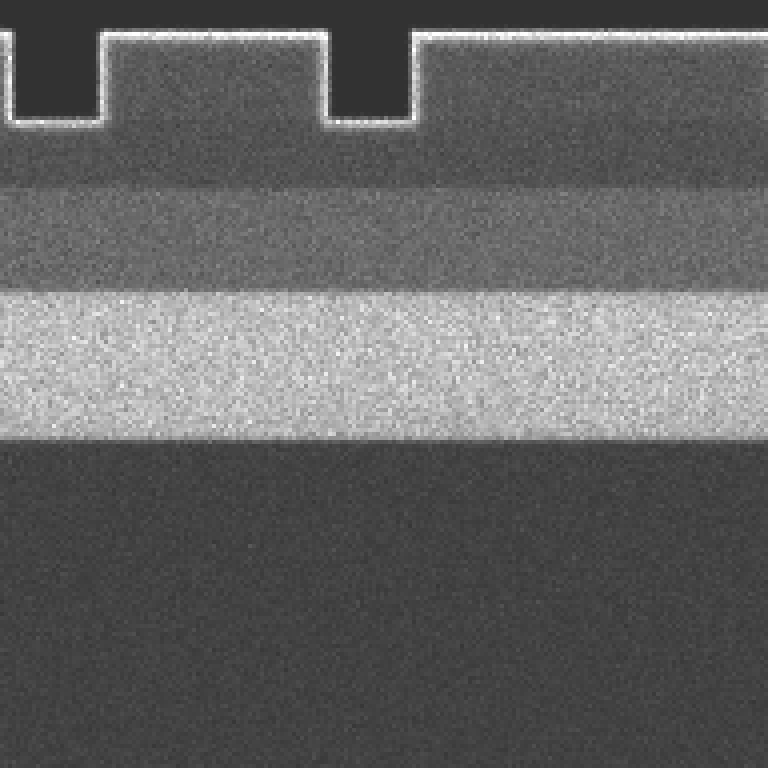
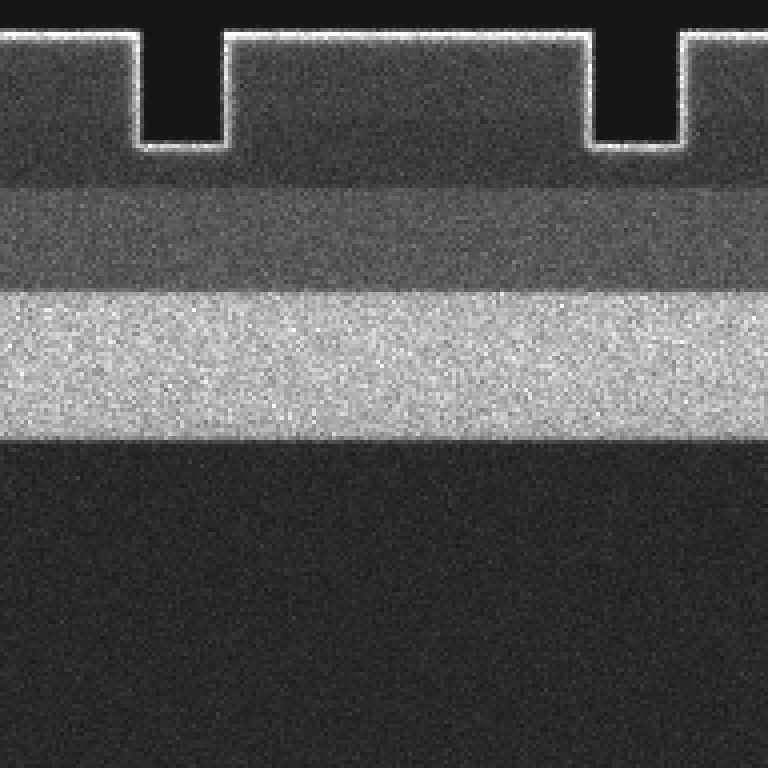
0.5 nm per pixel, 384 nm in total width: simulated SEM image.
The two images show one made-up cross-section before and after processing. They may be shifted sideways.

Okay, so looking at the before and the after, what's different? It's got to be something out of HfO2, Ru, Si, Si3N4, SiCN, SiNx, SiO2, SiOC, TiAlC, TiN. SiNx, removed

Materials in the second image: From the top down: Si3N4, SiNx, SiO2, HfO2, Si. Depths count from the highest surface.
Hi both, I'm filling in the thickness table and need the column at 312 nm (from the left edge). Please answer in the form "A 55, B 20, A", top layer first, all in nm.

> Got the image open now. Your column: empty 56, SiNx 22, SiO2 52, HfO2 74, Si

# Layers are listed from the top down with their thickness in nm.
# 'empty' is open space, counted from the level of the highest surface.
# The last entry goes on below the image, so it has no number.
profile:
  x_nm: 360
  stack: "Si3N4 44, SiNx 34, SiO2 52, HfO2 74, Si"